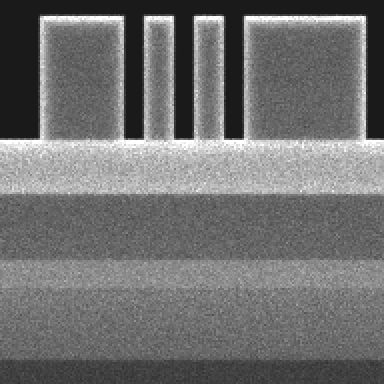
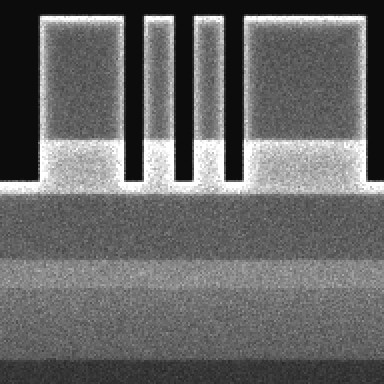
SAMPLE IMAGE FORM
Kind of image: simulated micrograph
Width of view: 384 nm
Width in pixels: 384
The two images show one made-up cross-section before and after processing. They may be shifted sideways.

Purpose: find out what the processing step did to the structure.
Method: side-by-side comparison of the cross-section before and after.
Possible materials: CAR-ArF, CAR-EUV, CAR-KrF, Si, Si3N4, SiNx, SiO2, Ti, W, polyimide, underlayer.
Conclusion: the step removed W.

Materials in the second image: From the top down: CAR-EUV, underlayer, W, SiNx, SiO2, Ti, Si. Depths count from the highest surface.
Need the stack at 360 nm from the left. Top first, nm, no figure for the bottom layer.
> CAR-EUV 72, underlayer 52, W 54, SiNx 66, SiO2 28, Ti 72, Si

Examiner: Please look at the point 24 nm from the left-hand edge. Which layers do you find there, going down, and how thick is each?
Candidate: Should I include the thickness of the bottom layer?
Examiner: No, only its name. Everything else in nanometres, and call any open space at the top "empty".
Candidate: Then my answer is empty 166, W 12, SiNx 66, SiO2 28, Ti 72, Si